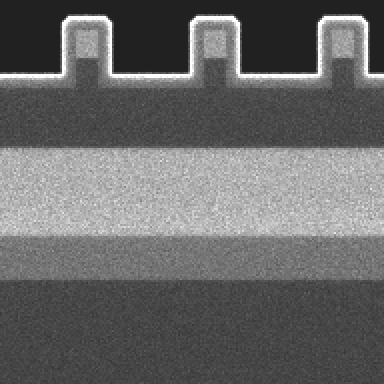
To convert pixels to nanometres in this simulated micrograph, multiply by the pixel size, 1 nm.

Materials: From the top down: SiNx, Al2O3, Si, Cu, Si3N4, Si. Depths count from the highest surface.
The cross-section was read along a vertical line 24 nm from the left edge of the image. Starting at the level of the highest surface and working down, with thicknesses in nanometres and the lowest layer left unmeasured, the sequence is empty 58, SiNx 14, Si 60, Cu 88, Si3N4 44, Si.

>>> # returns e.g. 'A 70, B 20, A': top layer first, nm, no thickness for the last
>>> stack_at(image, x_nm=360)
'SiNx 72, Si 60, Cu 88, Si3N4 44, Si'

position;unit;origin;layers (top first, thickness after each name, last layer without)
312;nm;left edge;empty 58, SiNx 14, Si 60, Cu 88, Si3N4 44, Si